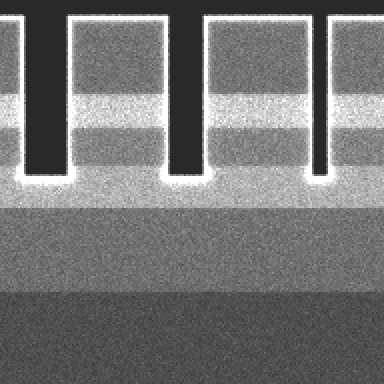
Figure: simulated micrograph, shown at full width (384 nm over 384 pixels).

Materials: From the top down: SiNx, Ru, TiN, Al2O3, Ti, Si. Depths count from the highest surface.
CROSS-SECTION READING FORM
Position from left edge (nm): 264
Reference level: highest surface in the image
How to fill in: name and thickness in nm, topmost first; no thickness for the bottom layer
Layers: SiNx 78, Ru 34, TiN 38, Al2O3 42, Ti 84, Si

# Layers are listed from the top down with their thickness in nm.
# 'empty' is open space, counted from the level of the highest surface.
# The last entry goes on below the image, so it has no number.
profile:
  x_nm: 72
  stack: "SiNx 78, Ru 34, TiN 38, Al2O3 42, Ti 84, Si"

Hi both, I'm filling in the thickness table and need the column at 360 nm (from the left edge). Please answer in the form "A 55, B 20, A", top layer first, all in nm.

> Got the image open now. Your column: SiNx 78, Ru 34, TiN 38, Al2O3 42, Ti 84, Si